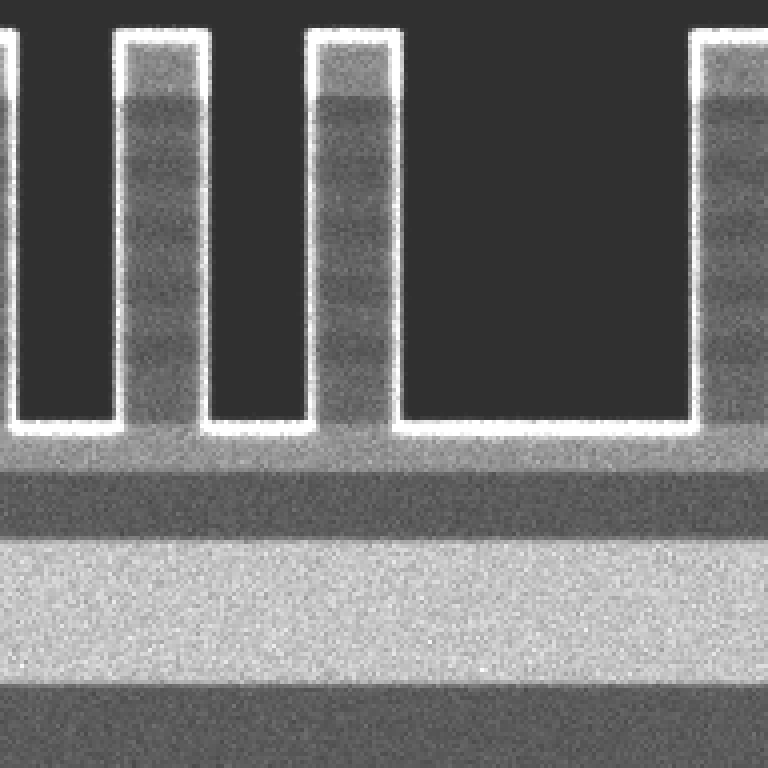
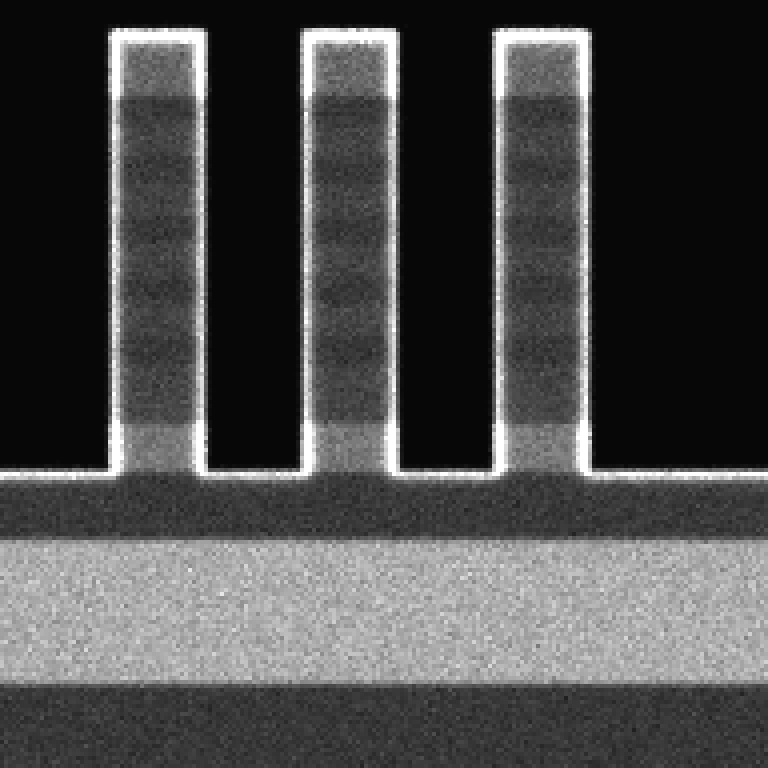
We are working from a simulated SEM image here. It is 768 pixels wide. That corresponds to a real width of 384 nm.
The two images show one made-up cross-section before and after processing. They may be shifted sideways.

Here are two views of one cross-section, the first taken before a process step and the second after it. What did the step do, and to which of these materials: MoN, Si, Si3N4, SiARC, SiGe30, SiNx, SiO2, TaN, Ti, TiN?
It removed Si3N4.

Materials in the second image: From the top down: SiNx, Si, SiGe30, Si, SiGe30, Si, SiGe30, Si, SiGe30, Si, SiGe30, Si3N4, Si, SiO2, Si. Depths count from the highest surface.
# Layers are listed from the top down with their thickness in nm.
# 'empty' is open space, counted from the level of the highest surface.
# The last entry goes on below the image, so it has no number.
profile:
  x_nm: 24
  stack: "empty 220, Si 34, SiO2 72, Si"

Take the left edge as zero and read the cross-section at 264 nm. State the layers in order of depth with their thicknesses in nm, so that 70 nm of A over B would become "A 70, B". SiNx 32, Si 14, SiGe30 16, Si 14, SiGe30 16, Si 14, SiGe30 16, Si 14, SiGe30 16, Si 14, SiGe30 30, Si3N4 24, Si 34, SiO2 72, Si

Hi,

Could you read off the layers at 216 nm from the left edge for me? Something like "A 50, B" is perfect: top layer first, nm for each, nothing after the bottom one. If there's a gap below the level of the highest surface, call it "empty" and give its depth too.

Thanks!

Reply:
empty 220, Si 34, SiO2 72, Si